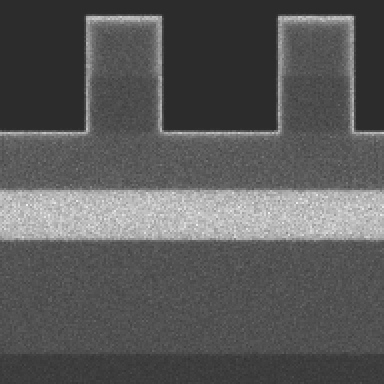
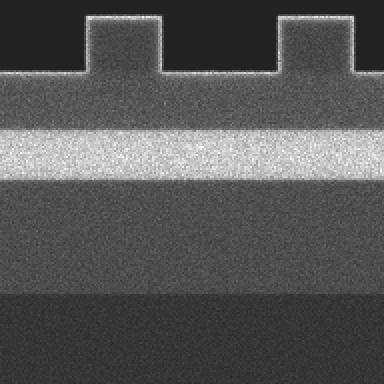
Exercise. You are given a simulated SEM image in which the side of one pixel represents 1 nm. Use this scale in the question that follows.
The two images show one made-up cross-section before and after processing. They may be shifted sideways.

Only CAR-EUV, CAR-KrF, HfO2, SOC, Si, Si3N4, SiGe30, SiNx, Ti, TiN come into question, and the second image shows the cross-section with SOC removed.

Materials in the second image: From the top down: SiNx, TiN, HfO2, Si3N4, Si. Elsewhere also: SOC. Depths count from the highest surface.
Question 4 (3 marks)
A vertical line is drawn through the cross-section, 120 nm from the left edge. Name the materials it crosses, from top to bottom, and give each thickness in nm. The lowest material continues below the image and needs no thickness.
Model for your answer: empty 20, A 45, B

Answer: SiNx 56, TiN 58, HfO2 50, Si3N4 114, Si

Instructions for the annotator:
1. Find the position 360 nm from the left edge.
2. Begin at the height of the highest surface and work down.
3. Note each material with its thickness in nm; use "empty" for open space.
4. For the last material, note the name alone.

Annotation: empty 56, TiN 58, HfO2 50, Si3N4 114, Si